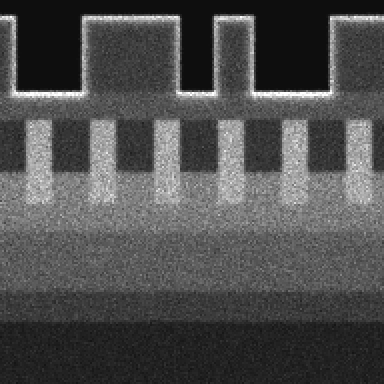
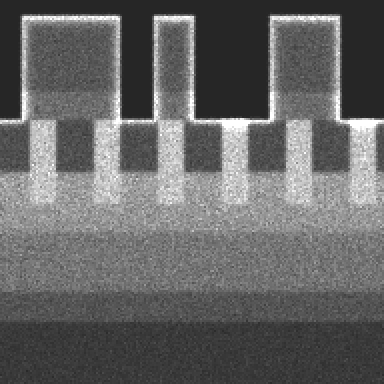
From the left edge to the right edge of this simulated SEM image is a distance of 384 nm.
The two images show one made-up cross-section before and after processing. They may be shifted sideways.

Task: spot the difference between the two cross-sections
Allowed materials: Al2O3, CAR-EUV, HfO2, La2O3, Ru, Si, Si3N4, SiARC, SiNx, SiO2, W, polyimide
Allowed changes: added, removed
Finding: removed SiO2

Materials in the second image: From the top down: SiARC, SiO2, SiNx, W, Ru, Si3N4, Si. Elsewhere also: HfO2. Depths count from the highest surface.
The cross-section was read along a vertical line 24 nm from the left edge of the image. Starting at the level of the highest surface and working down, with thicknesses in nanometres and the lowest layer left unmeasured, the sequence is SiARC 76, SiO2 28, SiNx 52, W 60, Ru 60, Si3N4 30, Si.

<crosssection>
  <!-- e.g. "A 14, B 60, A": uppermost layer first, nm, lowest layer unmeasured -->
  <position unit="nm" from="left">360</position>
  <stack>empty 104, HfO2 84, W 28, Ru 60, Si3N4 30, Si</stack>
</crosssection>